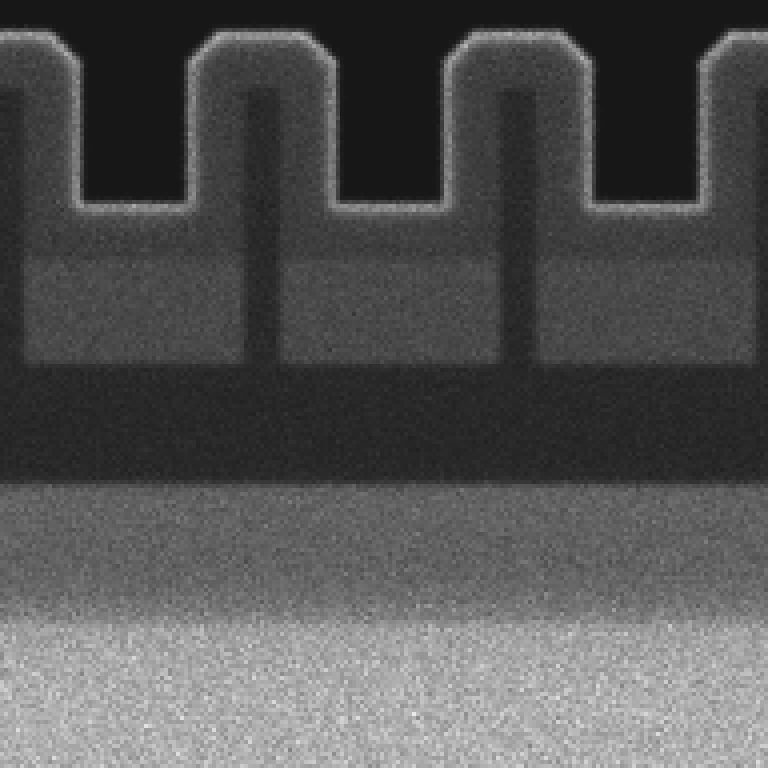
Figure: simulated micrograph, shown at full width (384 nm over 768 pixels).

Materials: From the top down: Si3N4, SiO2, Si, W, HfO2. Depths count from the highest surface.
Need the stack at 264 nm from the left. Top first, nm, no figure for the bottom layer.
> Si3N4 28, Si 198, W 70, HfO2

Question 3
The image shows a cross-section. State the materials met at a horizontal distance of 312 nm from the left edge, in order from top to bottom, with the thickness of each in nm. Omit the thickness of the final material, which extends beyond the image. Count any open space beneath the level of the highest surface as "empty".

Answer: empty 86, Si3N4 28, SiO2 52, Si 60, W 70, HfO2